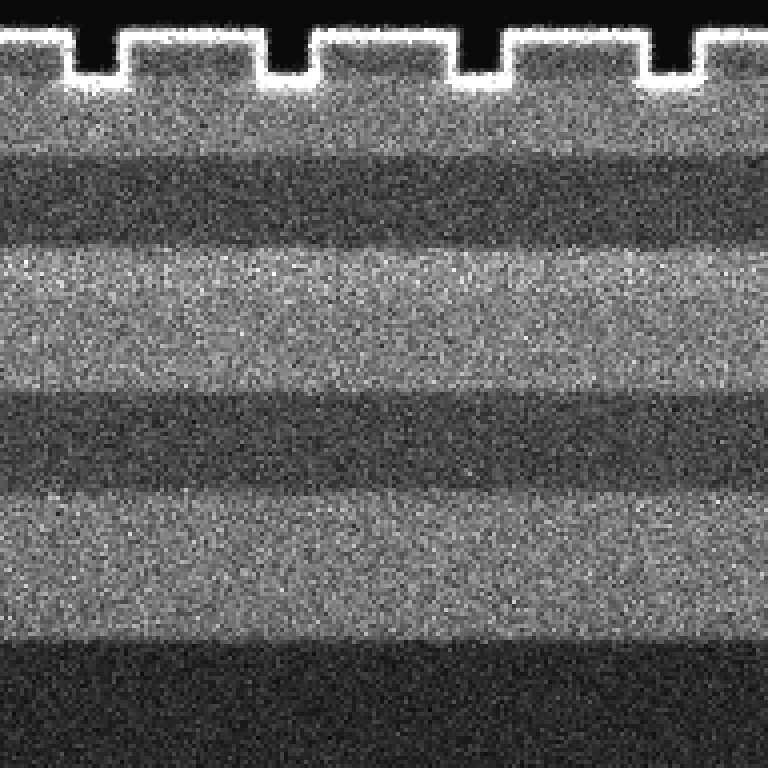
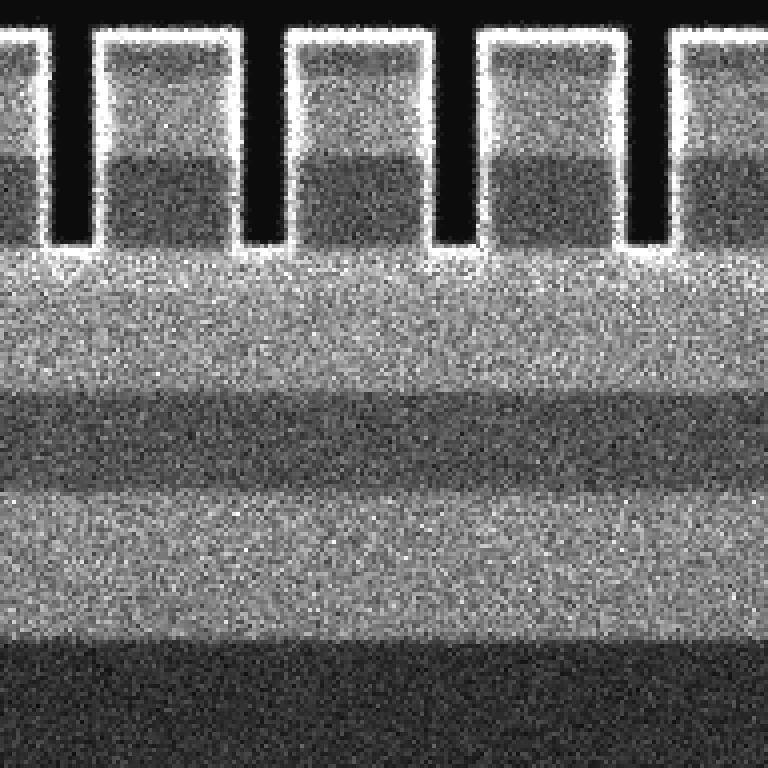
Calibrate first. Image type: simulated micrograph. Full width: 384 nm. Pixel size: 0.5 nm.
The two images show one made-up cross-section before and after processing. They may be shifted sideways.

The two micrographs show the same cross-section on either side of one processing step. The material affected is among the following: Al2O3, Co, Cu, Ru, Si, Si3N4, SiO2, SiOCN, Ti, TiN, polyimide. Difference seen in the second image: SiO2 and SiOCN removed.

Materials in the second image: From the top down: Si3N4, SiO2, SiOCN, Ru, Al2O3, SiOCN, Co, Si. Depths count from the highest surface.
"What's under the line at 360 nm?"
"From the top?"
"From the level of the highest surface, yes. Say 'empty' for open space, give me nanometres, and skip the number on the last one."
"Si3N4 22, SiO2 40, SiOCN 46, Ru 22, Al2O3 50, SiOCN 50, Co 74, Si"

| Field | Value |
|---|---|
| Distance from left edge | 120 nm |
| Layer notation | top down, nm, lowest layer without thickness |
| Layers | empty 108, Ru 22, Al2O3 50, SiOCN 50, Co 74, Si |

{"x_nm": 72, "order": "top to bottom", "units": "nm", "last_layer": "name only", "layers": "Si3N4 22, SiO2 40, SiOCN 46, Ru 22, Al2O3 50, SiOCN 50, Co 74, Si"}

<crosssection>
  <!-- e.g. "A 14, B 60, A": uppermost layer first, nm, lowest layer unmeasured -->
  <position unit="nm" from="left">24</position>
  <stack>empty 108, Ru 22, Al2O3 50, SiOCN 50, Co 74, Si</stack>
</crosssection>